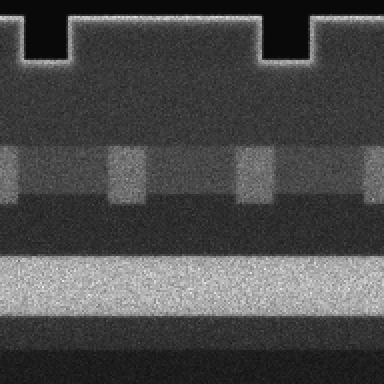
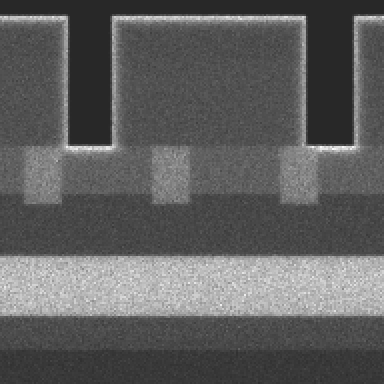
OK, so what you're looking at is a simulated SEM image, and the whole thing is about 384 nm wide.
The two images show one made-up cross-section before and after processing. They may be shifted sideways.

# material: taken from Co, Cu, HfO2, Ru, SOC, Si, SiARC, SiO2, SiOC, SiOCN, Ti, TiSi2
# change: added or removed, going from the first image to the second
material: SOC
change: removed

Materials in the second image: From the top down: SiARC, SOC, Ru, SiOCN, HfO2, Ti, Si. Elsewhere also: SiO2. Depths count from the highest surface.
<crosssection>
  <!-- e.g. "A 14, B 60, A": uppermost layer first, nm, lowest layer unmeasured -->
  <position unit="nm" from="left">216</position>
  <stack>SiARC 44, SOC 86, SiO2 48, SiOCN 62, HfO2 60, Ti 34, Si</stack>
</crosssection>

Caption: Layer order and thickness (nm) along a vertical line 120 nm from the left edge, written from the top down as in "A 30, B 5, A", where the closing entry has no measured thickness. SiARC 44, SOC 86, SiO2 48, SiOCN 62, HfO2 60, Ti 34, Si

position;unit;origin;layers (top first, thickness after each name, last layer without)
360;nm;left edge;SiARC 44, SOC 86, SiO2 48, SiOCN 62, HfO2 60, Ti 34, Si